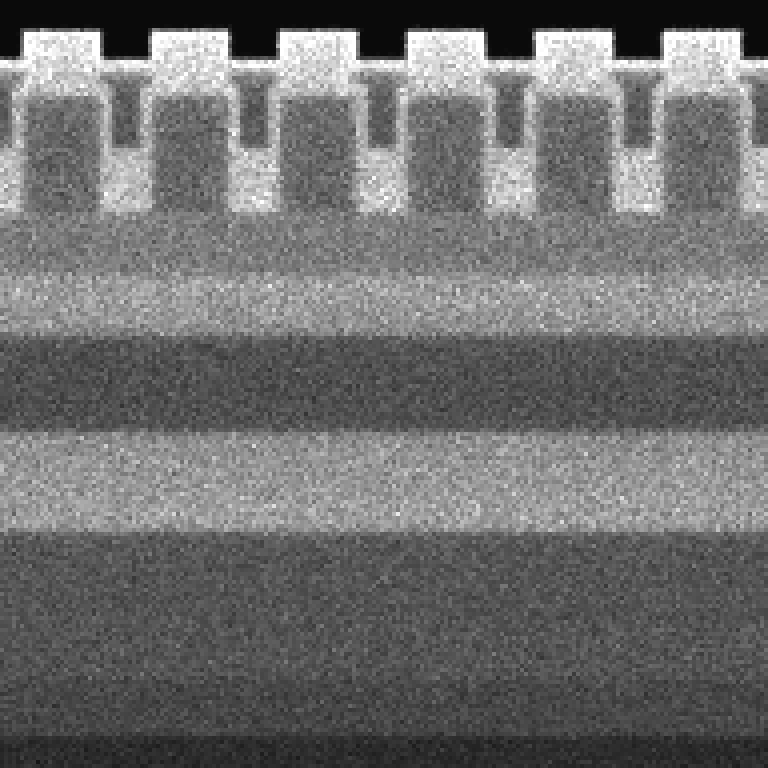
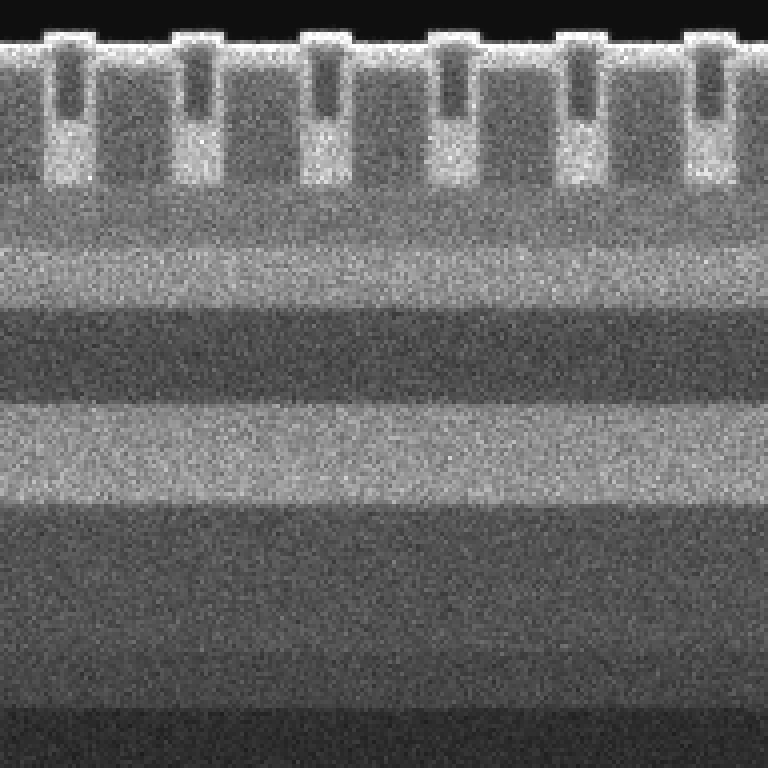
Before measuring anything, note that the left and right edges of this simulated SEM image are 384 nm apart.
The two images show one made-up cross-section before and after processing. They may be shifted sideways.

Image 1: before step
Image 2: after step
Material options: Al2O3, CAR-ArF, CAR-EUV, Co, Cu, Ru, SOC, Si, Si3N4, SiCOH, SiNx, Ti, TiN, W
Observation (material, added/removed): W, removed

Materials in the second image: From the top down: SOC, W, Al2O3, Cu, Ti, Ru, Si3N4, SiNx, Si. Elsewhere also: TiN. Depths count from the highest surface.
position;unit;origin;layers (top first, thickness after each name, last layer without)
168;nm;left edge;SOC 44, W 32, Al2O3 32, Cu 30, Ti 48, Ru 50, Si3N4 74, SiNx 28, Si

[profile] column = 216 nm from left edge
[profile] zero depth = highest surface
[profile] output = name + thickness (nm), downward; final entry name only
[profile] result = SOC 12, W 64, Al2O3 32, Cu 30, Ti 48, Ru 50, Si3N4 74, SiNx 28, Si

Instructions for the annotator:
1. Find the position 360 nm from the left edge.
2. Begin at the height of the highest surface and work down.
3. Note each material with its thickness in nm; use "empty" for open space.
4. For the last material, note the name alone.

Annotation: SOC 44, W 32, Al2O3 32, Cu 30, Ti 48, Ru 50, Si3N4 74, SiNx 28, Si